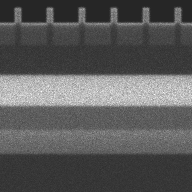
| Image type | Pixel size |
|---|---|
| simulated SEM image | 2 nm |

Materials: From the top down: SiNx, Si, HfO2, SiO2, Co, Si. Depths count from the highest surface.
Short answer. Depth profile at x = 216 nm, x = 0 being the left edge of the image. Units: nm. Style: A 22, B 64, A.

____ empty 30, SiNx 44, Si 60, HfO2 62, SiO2 48, Co 48, Si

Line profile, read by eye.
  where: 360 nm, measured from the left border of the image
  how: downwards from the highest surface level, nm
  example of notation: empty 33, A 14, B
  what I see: Si 134, HfO2 62, SiO2 48, Co 48, Si